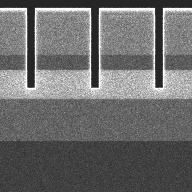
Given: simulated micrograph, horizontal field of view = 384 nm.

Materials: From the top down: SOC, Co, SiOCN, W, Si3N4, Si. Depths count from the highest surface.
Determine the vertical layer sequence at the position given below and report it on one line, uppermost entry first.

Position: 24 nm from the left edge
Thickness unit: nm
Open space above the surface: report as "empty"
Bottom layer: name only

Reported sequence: SOC 14, Co 80, SiOCN 30, W 58, Si3N4 84, Si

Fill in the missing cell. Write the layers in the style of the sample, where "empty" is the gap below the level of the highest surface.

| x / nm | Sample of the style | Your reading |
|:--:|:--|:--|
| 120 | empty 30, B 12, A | SOC 14, Co 80, SiOCN 30, W 58, Si3N4 84, Si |